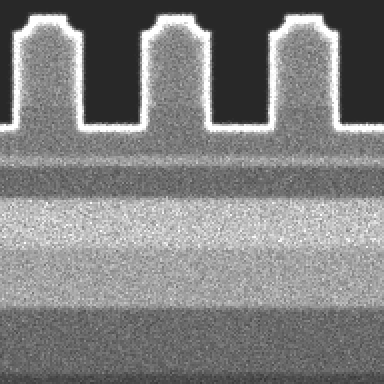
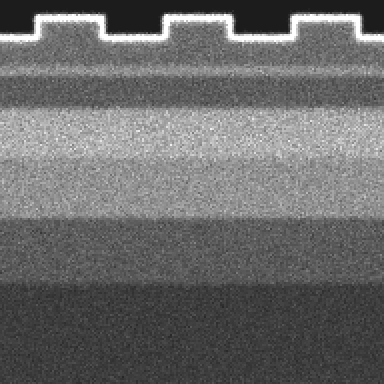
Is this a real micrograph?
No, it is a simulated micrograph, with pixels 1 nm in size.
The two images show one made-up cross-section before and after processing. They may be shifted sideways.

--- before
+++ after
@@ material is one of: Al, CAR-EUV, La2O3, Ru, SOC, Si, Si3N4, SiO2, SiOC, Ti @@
SOC removed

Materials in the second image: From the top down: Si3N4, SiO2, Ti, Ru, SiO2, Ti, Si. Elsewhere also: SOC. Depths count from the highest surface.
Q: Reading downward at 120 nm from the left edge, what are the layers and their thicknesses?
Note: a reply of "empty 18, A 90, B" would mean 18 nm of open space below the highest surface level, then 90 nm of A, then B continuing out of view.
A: empty 20, Si3N4 30, SiO2 10, Ti 32, Ru 50, SiO2 60, Ti 66, Si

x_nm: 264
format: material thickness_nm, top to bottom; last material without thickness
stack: empty 20, Si3N4 30, SiO2 10, Ti 32, Ru 50, SiO2 60, Ti 66, Si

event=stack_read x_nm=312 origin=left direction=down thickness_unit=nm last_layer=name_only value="Si3N4 50, SiO2 10, Ti 32, Ru 50, SiO2 60, Ti 66, Si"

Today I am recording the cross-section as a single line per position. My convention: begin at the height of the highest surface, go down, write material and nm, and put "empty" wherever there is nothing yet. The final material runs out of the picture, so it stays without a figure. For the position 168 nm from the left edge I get Si3N4 50, SiO2 10, Ti 32, Ru 50, SiO2 60, Ti 66, Si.